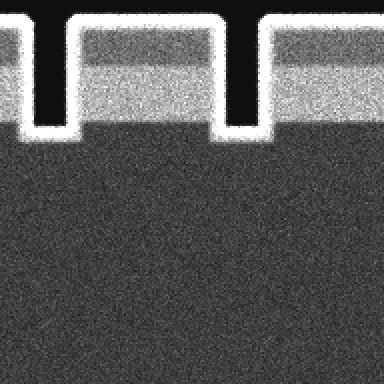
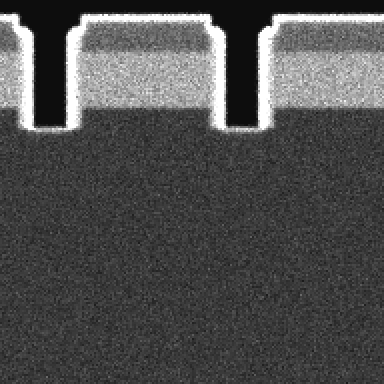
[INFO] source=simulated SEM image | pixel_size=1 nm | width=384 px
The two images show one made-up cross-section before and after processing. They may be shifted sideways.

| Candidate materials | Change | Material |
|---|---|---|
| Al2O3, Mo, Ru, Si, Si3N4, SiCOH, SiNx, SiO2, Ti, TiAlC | removed | Al2O3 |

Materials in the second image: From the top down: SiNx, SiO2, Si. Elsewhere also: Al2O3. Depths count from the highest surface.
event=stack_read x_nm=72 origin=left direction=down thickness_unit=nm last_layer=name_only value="empty 14, Al2O3 98, Si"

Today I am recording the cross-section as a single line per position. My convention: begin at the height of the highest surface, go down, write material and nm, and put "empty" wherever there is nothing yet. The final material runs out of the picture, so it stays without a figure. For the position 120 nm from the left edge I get SiNx 36, SiO2 56, Si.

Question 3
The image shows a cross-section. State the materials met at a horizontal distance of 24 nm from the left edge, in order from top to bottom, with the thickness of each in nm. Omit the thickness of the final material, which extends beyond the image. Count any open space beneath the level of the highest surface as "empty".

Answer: empty 12, Al2O3 100, Si